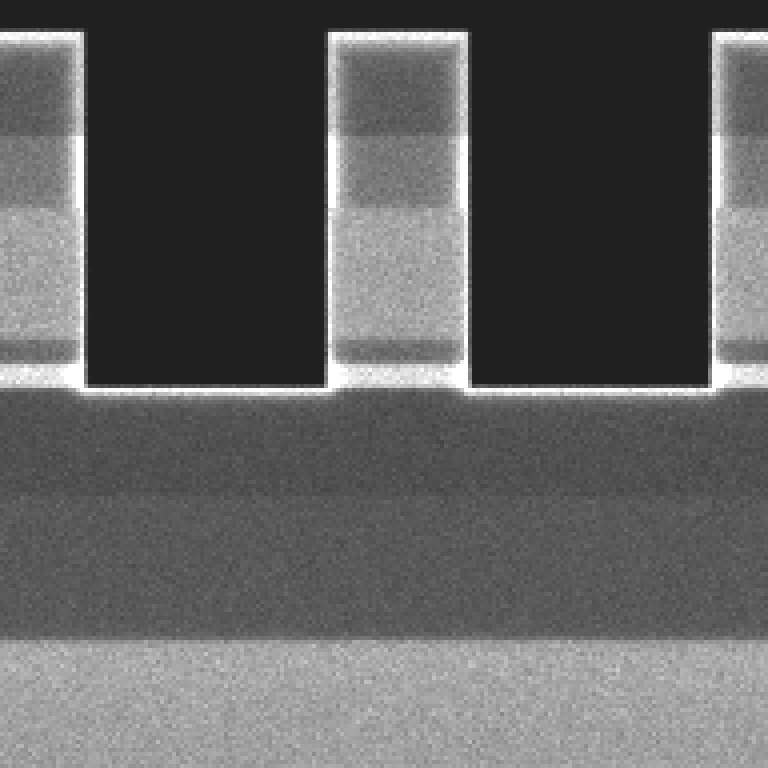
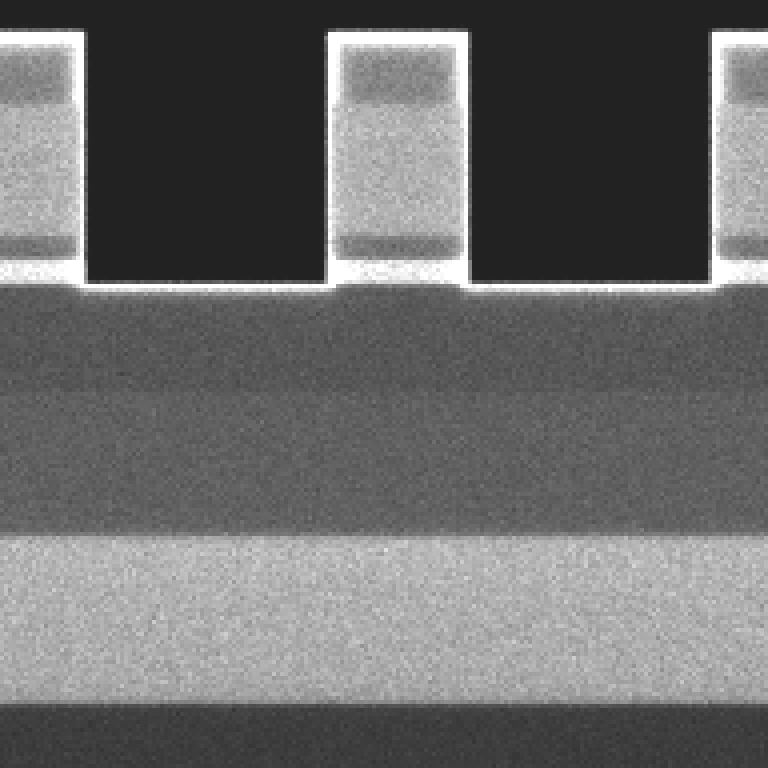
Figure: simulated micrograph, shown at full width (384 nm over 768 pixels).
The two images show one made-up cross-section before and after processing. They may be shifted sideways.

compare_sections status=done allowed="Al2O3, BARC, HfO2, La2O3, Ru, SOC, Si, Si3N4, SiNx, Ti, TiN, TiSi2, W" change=removed material="SOC"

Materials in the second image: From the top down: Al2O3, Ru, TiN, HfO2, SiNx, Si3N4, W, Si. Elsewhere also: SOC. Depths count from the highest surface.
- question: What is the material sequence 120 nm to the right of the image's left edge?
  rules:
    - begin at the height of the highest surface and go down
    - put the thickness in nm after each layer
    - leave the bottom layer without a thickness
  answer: empty 126, SiNx 54, Si3N4 72, W 84, Si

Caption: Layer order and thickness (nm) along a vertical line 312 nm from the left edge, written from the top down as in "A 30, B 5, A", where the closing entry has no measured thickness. empty 126, SiNx 54, Si3N4 72, W 84, Si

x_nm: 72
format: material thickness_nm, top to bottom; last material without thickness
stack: empty 126, SiNx 54, Si3N4 72, W 84, Si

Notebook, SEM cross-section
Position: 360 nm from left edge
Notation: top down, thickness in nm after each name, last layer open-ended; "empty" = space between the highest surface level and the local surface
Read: Al2O3 36, Ru 66, TiN 12, HfO2 12, SiNx 54, Si3N4 72, W 84, Si